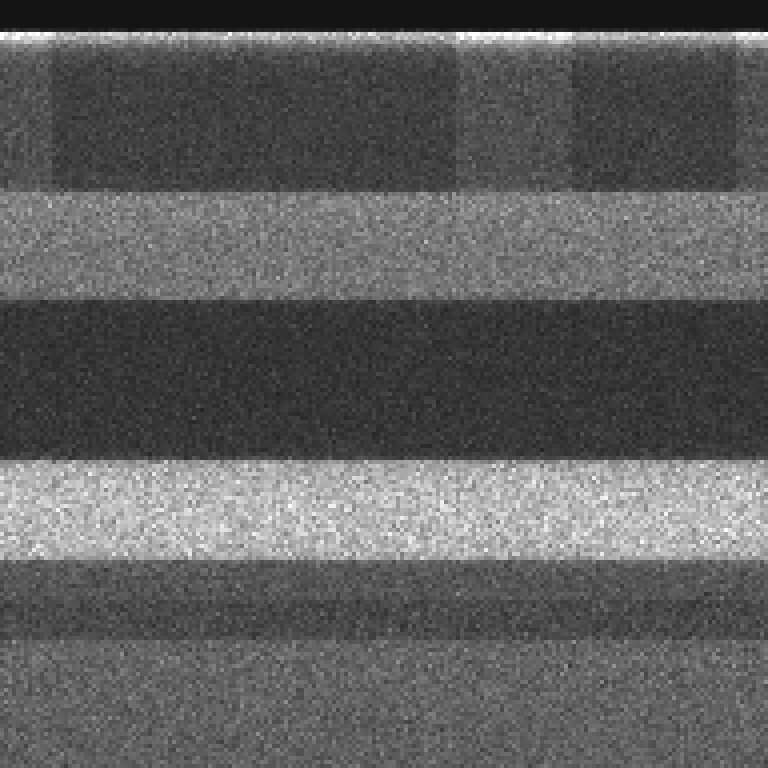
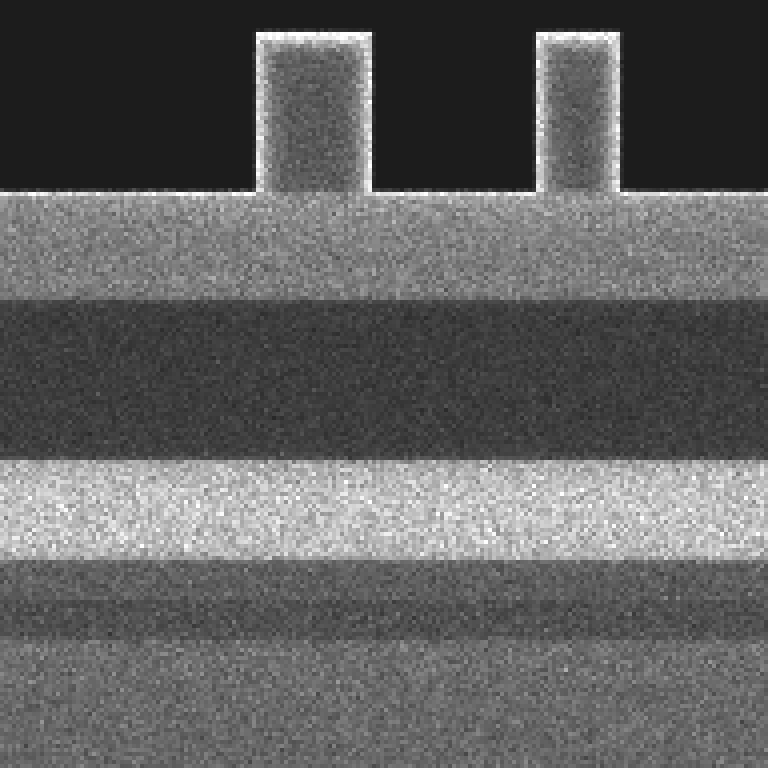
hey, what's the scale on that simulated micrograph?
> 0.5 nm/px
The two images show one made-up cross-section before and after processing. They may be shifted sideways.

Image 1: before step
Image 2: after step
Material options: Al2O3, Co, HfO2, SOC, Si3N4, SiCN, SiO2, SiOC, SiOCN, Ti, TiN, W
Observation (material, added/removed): SOC, removed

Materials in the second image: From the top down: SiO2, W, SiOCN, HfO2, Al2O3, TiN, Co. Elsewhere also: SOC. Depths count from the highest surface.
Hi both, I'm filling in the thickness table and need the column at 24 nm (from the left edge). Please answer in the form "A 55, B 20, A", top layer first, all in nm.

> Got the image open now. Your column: empty 80, W 54, SiOCN 80, HfO2 50, Al2O3 20, TiN 20, Co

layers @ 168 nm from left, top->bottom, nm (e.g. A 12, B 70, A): SiO2 80, W 54, SiOCN 80, HfO2 50, Al2O3 20, TiN 20, Co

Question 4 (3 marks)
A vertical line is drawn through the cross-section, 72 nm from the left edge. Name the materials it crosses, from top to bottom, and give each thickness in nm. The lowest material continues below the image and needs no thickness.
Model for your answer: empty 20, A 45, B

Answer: empty 80, W 54, SiOCN 80, HfO2 50, Al2O3 20, TiN 20, Co